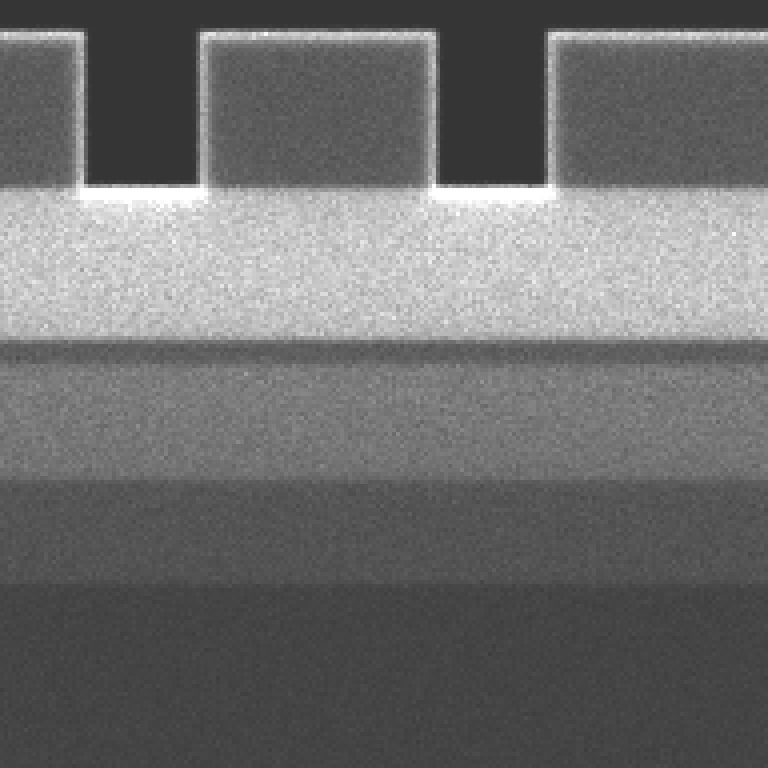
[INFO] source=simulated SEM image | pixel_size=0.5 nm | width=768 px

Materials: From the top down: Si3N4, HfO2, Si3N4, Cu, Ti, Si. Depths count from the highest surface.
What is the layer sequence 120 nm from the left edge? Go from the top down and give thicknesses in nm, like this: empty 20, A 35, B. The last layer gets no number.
Si3N4 78, HfO2 76, Si3N4 12, Cu 58, Ti 52, Si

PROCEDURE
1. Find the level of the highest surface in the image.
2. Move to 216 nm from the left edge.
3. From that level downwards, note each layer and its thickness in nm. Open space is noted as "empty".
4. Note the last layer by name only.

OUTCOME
Si3N4 78, HfO2 76, Si3N4 12, Cu 58, Ti 52, Si